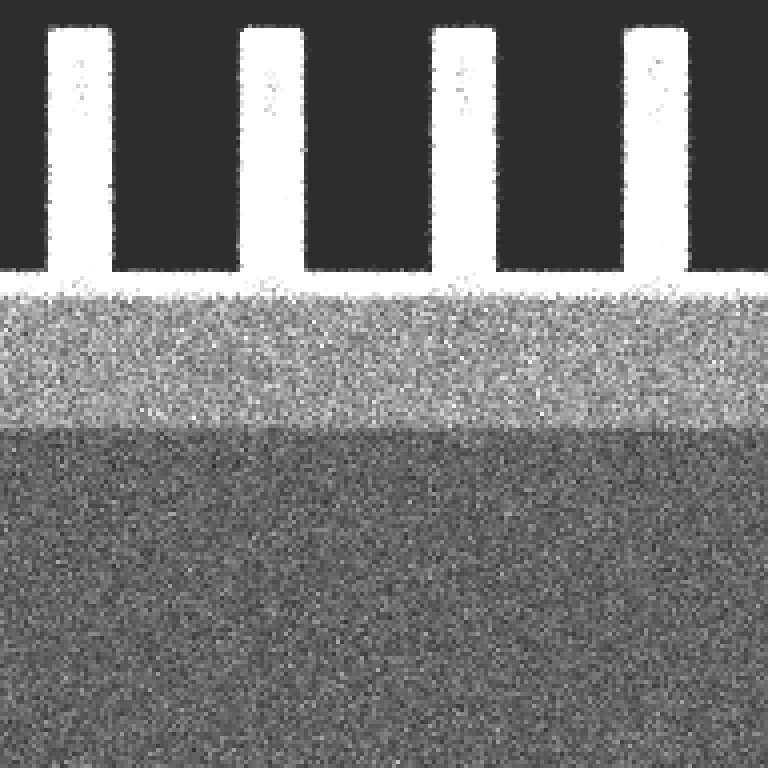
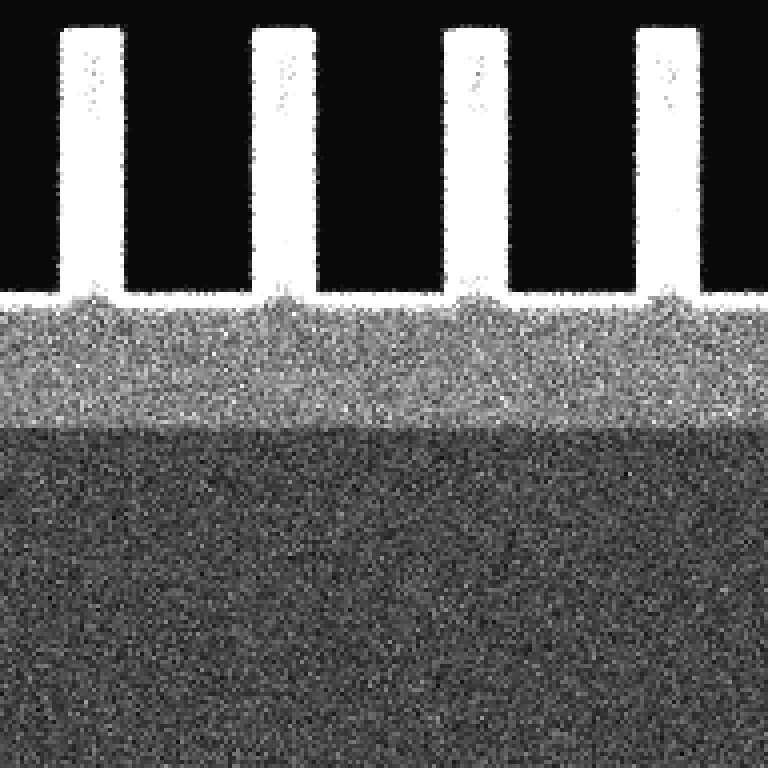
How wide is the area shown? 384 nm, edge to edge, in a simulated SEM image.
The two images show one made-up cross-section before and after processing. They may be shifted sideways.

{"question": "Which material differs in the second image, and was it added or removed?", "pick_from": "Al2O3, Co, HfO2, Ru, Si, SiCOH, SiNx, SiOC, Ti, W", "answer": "Co, removed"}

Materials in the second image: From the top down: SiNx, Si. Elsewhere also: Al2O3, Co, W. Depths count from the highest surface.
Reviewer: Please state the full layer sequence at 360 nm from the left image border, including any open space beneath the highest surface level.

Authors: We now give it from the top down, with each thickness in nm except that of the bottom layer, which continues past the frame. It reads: empty 132, SiNx 66, Si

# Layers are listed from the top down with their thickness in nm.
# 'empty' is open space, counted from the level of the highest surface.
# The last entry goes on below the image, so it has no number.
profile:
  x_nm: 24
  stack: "empty 132, SiNx 66, Si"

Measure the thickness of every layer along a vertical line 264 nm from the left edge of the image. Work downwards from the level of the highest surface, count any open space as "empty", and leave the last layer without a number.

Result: empty 132, SiNx 66, Si